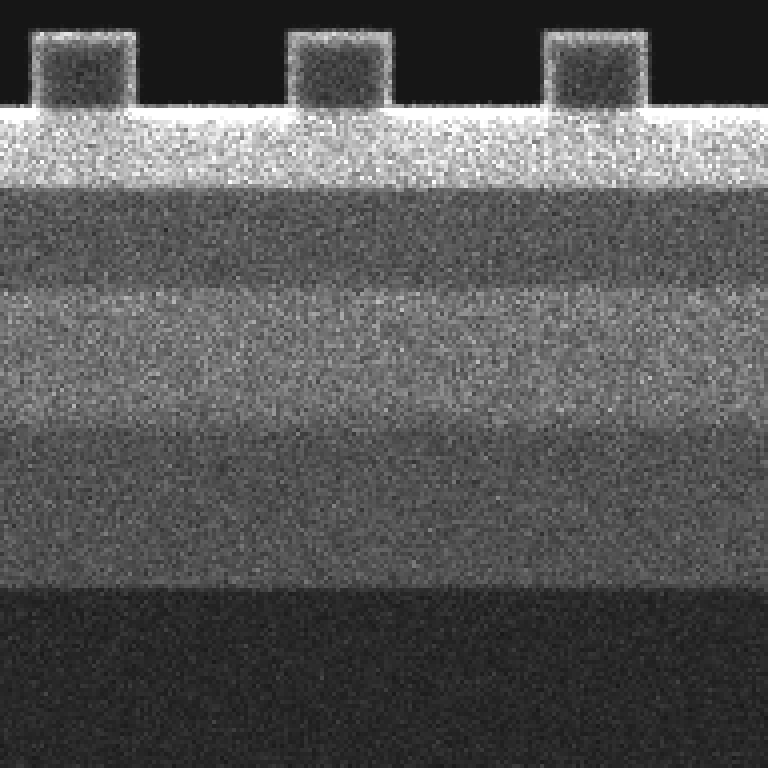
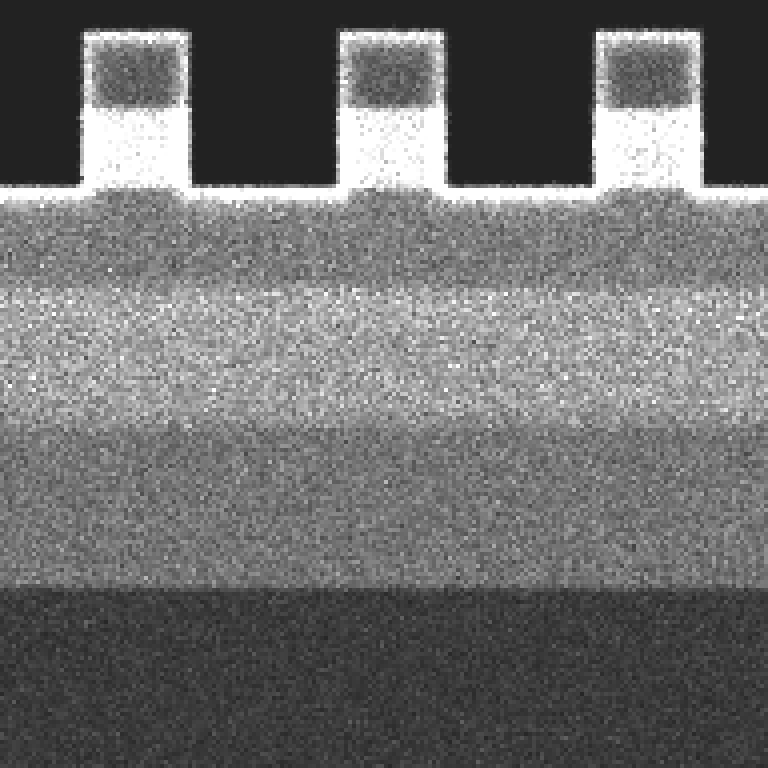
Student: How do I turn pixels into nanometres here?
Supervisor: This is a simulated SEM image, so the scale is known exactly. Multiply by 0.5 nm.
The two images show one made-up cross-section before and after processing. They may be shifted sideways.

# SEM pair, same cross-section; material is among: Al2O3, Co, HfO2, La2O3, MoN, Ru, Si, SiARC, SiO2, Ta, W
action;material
removed;HfO2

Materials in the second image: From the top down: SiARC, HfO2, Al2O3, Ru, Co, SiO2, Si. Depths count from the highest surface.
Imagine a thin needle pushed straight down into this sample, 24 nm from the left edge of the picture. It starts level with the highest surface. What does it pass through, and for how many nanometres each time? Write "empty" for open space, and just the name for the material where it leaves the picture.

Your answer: empty 78, Al2O3 50, Ru 60, Co 10, SiO2 80, Si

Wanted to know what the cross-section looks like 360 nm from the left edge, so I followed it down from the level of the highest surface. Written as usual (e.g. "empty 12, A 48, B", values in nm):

empty 78, Al2O3 50, Ru 60, Co 10, SiO2 80, Si